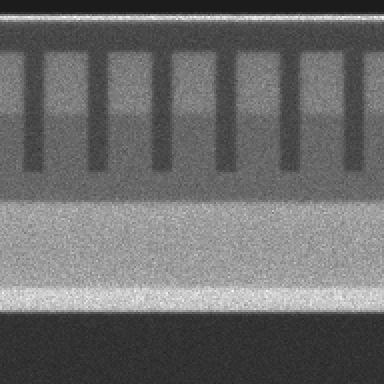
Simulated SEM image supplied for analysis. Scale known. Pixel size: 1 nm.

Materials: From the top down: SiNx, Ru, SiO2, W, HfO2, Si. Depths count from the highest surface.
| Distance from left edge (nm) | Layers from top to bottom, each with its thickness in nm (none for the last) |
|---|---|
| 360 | SiNx 156, SiO2 30, W 86, HfO2 24, Si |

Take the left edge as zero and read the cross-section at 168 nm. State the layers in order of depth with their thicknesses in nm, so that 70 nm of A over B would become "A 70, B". SiNx 156, SiO2 30, W 86, HfO2 24, Si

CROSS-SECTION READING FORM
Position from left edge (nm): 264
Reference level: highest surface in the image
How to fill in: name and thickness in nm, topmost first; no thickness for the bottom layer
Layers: SiNx 36, Ru 62, SiO2 88, W 86, HfO2 24, Si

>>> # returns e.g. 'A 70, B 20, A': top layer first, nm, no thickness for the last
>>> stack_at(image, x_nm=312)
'SiNx 36, Ru 62, SiO2 88, W 86, HfO2 24, Si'